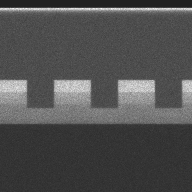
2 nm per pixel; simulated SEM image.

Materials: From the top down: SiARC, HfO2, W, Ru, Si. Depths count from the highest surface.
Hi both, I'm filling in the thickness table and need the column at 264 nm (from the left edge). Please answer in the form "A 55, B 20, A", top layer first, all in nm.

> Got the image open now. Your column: SiARC 144, HfO2 24, W 24, Ru 40, Si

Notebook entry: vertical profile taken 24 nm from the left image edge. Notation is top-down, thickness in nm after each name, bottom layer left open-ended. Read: SiARC 144, HfO2 24, W 24, Ru 40, Si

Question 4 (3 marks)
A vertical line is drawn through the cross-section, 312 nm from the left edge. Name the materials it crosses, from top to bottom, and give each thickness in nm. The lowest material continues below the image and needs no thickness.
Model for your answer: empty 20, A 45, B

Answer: SiARC 200, Ru 32, Si